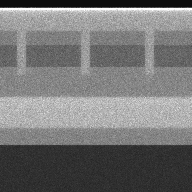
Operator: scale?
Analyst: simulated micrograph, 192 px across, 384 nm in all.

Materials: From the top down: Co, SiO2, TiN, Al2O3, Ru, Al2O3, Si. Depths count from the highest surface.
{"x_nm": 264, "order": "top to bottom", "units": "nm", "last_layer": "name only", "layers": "Co 46, SiO2 28, TiN 44, Al2O3 60, Ru 62, Al2O3 34, Si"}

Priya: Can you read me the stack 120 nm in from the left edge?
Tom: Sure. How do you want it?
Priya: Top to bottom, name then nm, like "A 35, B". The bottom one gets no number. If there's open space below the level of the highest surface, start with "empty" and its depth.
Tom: Co 46, SiO2 28, TiN 44, Al2O3 60, Ru 62, Al2O3 34, Si